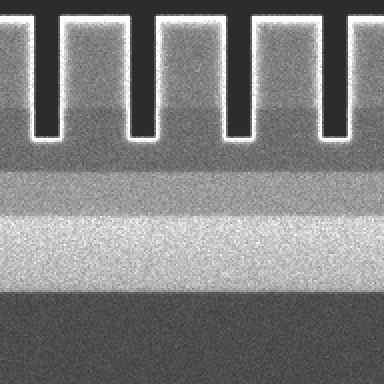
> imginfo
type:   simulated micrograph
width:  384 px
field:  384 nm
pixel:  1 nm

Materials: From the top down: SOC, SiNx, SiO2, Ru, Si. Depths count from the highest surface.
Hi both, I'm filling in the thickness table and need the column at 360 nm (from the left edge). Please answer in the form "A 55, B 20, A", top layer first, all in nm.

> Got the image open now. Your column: SOC 92, SiNx 64, SiO2 44, Ru 76, Si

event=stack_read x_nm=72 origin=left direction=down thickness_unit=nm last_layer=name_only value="SOC 92, SiNx 64, SiO2 44, Ru 76, Si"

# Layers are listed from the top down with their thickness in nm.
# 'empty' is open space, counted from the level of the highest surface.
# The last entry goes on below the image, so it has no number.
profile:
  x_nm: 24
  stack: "SOC 92, SiNx 64, SiO2 44, Ru 76, Si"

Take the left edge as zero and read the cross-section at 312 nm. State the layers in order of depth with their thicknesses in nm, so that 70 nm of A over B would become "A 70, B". SOC 92, SiNx 64, SiO2 44, Ru 76, Si